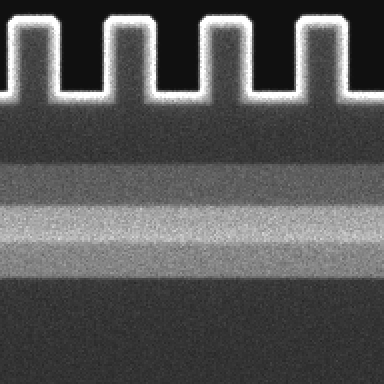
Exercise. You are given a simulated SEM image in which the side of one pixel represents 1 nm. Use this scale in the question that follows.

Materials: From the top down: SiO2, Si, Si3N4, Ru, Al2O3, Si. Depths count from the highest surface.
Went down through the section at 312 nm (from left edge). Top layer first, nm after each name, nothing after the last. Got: SiO2 12, Si 136, Si3N4 42, Ru 36, Al2O3 36, Si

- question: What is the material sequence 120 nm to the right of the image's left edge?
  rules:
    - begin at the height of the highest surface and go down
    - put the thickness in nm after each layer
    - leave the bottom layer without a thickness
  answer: SiO2 12, Si 136, Si3N4 42, Ru 36, Al2O3 36, Si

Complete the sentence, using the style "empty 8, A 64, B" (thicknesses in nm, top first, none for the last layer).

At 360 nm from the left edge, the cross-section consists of empty 76, SiO2 12, Si 60, Si3N4 42, Ru 36, Al2O3 36, Si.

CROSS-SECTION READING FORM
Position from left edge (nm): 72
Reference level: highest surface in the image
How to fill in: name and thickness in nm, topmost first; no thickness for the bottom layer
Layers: empty 76, SiO2 12, Si 60, Si3N4 42, Ru 36, Al2O3 36, Si